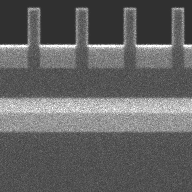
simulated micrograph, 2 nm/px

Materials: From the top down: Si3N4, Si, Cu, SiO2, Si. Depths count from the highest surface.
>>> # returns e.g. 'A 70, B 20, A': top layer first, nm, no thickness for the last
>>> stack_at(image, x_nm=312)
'empty 74, Si3N4 46, Si 60, Cu 30, SiO2 38, Si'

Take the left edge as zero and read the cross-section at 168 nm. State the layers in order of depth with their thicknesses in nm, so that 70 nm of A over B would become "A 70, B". Si 180, Cu 30, SiO2 38, Si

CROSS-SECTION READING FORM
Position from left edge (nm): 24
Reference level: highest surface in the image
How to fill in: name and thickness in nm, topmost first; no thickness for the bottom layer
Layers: empty 74, Si3N4 46, Si 60, Cu 30, SiO2 38, Si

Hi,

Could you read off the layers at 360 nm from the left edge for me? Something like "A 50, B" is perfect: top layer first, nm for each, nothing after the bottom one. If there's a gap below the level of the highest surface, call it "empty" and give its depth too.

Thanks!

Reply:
Si 180, Cu 30, SiO2 38, Si